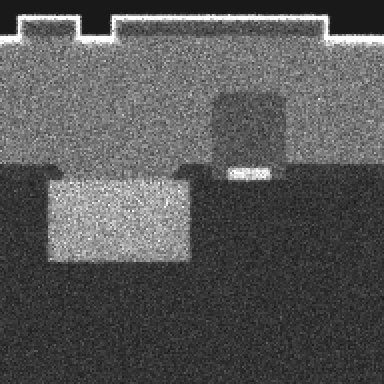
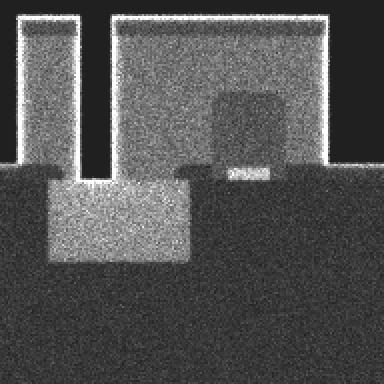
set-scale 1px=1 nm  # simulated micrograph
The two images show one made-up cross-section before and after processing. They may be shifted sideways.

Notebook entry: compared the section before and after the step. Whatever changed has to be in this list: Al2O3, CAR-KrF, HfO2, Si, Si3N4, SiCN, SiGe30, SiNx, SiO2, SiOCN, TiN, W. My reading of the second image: SiO2 removed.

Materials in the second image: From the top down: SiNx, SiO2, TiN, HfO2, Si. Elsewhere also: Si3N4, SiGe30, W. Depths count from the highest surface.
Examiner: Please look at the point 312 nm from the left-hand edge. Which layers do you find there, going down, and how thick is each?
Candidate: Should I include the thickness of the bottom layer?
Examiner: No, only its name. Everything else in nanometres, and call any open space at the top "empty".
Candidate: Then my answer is SiNx 20, SiO2 128, SiGe30 16, Si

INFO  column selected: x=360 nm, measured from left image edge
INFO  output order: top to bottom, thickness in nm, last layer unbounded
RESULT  empty 148, SiGe30 16, Si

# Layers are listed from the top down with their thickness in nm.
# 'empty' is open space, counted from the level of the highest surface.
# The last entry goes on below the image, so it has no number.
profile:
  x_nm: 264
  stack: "SiNx 20, SiO2 56, TiN 76, HfO2 12, Si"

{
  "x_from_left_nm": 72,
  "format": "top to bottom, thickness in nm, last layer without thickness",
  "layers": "SiNx 20, SiO2 144, W 82, Si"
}